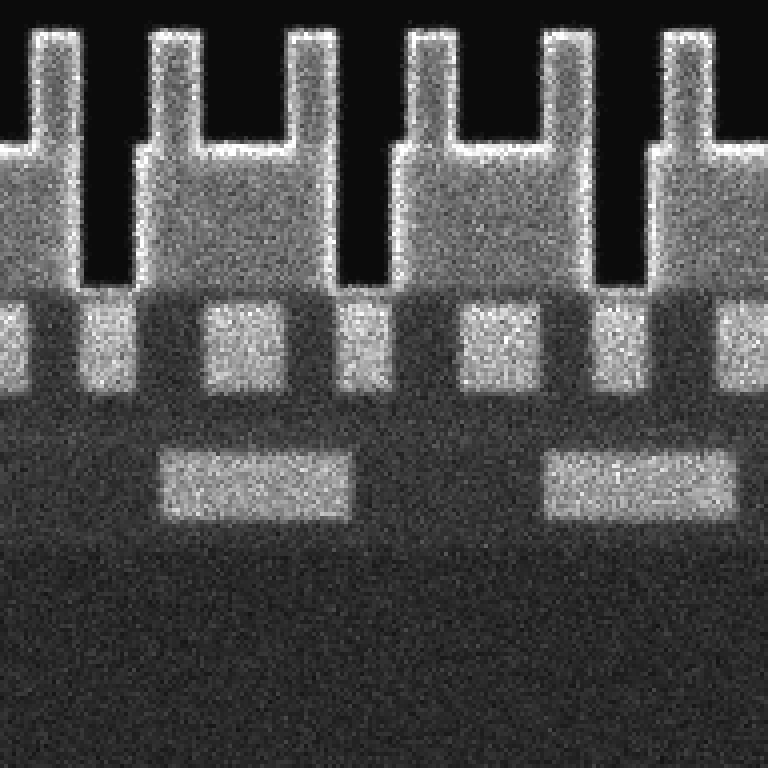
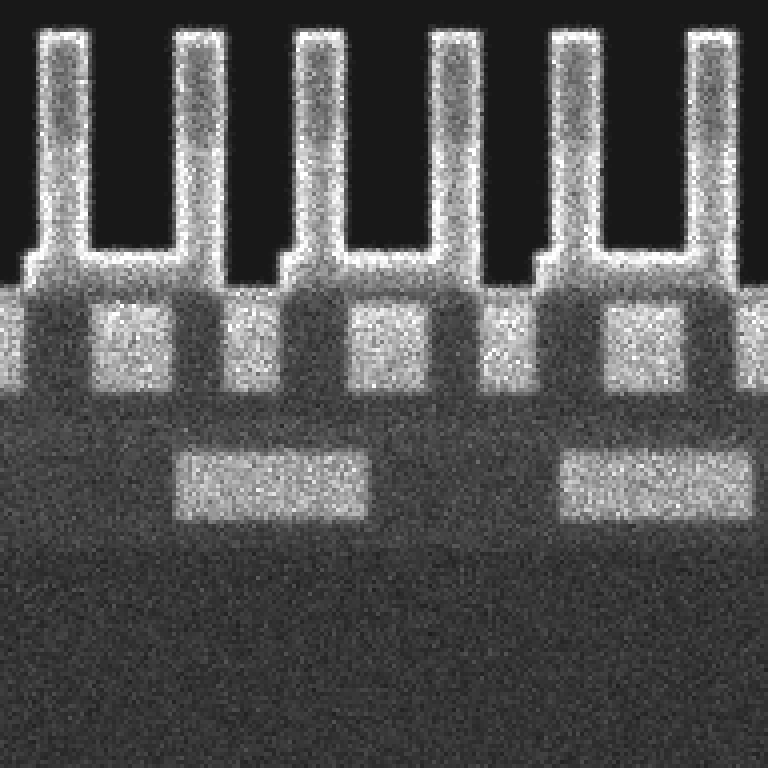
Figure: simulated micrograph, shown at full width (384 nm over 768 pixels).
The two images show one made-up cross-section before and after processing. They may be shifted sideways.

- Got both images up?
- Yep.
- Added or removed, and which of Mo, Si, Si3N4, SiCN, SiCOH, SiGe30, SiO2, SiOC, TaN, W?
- removed, SiO2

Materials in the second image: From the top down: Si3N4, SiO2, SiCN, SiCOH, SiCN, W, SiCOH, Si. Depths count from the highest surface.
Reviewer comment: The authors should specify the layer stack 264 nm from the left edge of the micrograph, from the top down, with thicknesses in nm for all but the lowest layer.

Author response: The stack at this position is empty 128, SiCN 8, W 44, SiCOH 14, SiCN 16, SiCOH 48, Si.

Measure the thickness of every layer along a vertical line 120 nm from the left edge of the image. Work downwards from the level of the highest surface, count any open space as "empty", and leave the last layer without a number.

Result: empty 128, SiCN 8, W 44, SiCOH 14, SiCN 16, W 34, SiCOH 14, Si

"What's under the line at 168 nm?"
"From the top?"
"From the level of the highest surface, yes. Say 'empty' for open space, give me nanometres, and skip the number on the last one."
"Si3N4 56, SiO2 72, SiCN 8, SiCOH 58, SiCN 16, W 34, SiCOH 14, Si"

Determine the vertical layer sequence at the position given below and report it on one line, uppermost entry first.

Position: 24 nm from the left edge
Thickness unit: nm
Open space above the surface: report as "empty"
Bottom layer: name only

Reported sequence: Si3N4 56, SiO2 72, SiCN 8, SiCOH 58, SiCN 16, SiCOH 48, Si